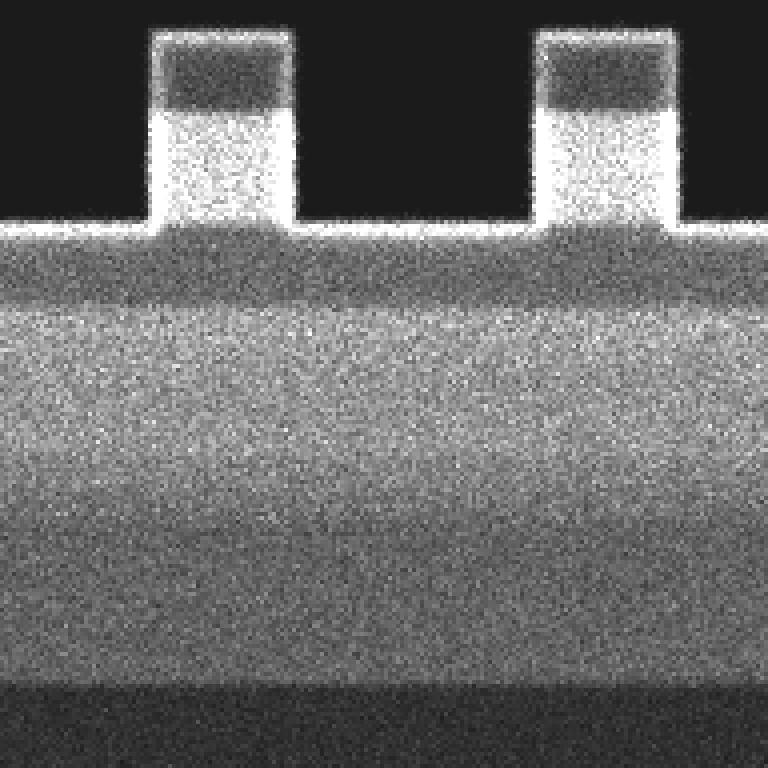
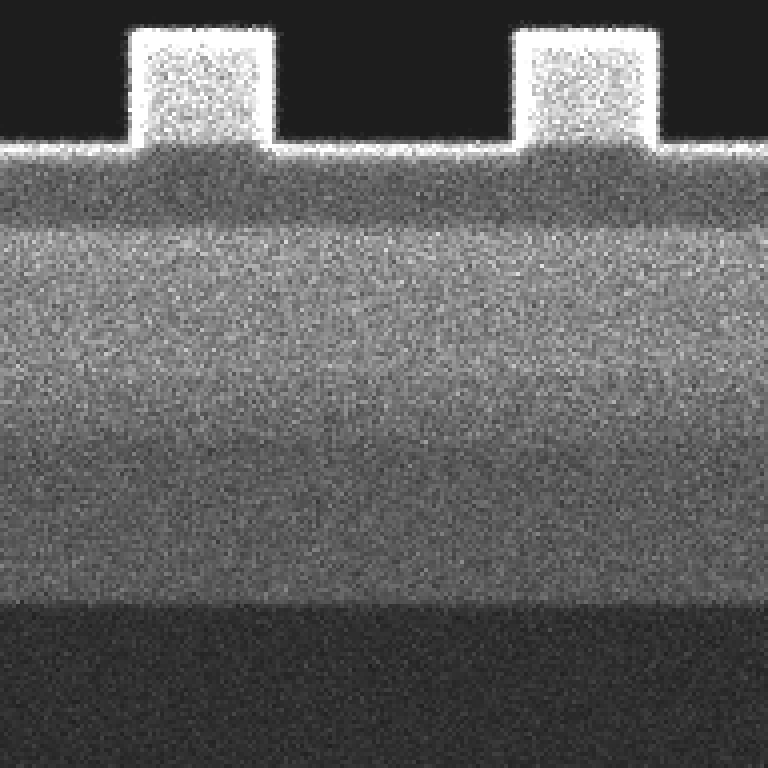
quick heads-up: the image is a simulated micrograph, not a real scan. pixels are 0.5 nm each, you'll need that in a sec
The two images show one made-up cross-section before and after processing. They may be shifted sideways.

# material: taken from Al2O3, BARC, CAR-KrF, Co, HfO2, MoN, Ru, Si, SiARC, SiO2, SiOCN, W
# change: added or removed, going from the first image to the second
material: SiARC
change: removed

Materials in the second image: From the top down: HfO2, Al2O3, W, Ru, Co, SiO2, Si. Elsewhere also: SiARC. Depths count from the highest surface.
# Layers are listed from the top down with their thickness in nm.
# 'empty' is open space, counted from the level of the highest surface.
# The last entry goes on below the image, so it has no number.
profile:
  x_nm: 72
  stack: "HfO2 56, Al2O3 42, W 74, Ru 16, Co 16, SiO2 82, Si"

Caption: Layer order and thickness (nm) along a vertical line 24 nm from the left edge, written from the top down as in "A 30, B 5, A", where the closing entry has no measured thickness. empty 56, Al2O3 42, W 74, Ru 16, Co 16, SiO2 82, Si